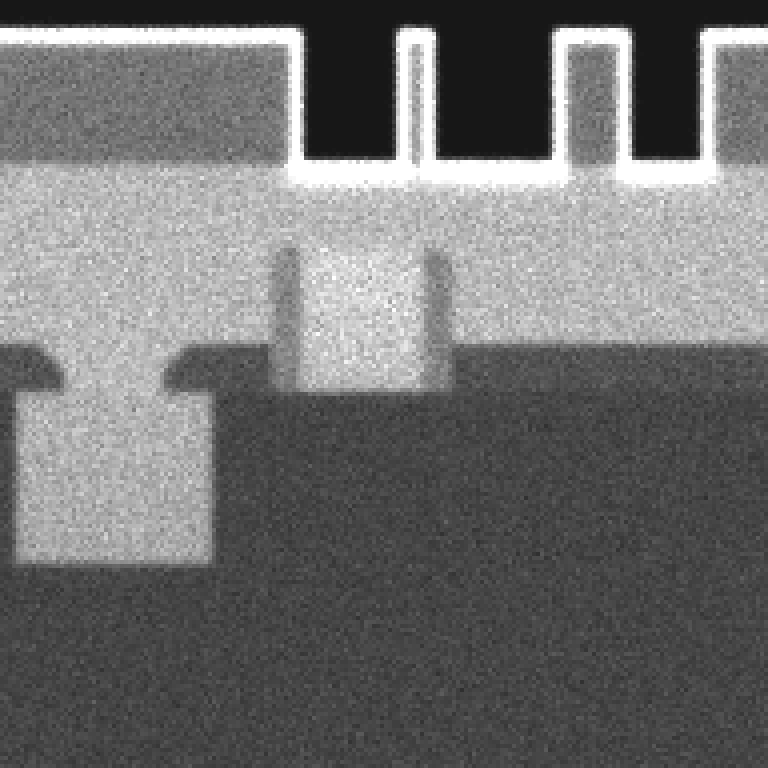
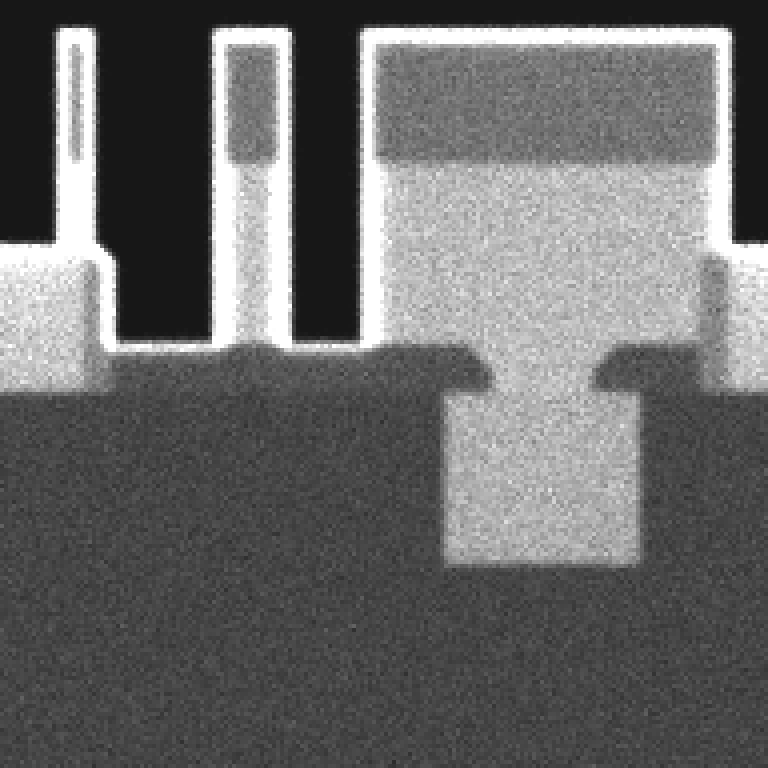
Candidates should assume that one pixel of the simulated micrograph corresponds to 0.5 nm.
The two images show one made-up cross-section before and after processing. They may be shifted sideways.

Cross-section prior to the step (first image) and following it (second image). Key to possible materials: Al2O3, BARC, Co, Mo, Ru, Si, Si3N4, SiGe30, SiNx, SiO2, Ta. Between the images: SiO2 was removed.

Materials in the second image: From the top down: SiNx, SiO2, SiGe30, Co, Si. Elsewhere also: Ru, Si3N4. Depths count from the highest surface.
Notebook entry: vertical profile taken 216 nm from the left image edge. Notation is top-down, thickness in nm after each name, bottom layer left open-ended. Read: SiNx 66, SiO2 90, SiGe30 24, Si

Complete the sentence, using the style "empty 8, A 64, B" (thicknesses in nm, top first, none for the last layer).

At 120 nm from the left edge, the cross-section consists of SiNx 66, SiO2 90, SiGe30 24, Si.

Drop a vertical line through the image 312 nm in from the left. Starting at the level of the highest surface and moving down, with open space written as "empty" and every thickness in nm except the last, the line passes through SiNx 66, SiO2 90, SiGe30 24, Co 86, Si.